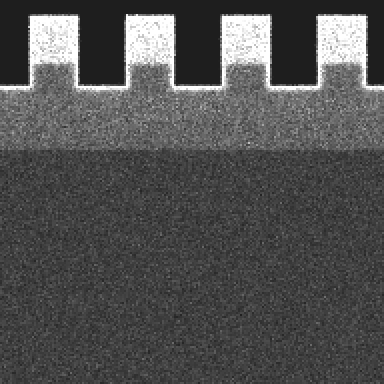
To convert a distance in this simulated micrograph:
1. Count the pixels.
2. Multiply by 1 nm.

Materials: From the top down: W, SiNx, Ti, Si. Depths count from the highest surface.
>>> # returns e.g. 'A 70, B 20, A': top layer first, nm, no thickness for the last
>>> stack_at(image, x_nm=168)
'W 48, SiNx 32, Ti 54, Si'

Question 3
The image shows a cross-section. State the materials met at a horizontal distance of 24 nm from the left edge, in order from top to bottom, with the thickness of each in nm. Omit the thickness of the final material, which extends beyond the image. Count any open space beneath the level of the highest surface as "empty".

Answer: empty 70, SiNx 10, Ti 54, Si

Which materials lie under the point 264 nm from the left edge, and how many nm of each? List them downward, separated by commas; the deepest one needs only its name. W 48, SiNx 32, Ti 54, Si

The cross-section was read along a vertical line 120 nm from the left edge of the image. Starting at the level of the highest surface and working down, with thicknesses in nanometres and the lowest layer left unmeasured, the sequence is empty 70, SiNx 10, Ti 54, Si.